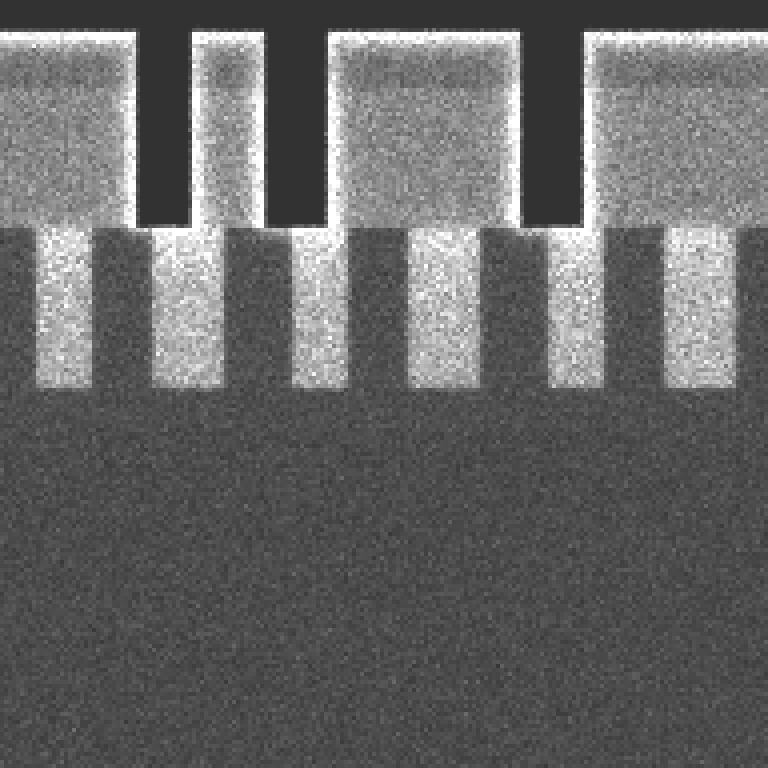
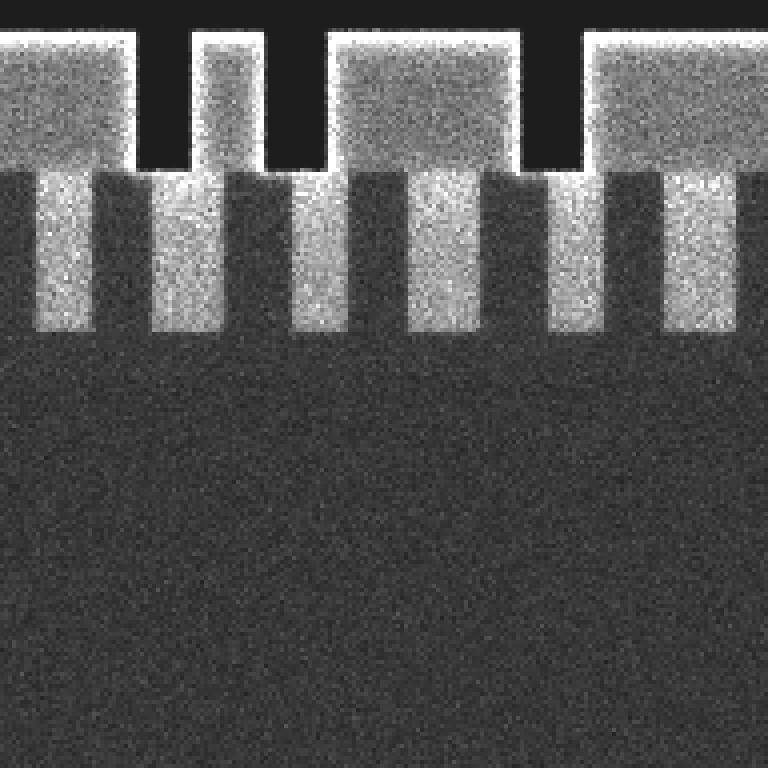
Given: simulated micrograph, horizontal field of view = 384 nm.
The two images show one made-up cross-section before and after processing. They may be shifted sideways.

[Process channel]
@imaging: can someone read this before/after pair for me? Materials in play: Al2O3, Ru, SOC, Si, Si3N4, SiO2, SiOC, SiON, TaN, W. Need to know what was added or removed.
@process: SOC removed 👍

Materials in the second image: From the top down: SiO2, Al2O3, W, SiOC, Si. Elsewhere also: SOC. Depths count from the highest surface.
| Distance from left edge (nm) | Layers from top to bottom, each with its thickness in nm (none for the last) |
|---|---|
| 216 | SiO2 60, Al2O3 10, W 80, SiOC 22, Si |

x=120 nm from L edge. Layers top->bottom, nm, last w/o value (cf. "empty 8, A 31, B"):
SiO2 60, Al2O3 10, SiOC 102, Si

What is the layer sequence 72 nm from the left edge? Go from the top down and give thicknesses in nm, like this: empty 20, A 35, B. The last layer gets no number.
empty 70, SiOC 102, Si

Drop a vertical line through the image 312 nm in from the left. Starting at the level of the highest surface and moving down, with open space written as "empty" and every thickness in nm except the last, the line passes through SiO2 60, Al2O3 10, SiOC 102, Si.